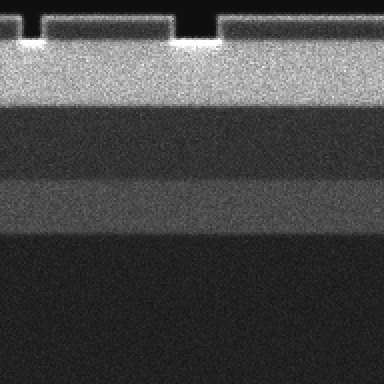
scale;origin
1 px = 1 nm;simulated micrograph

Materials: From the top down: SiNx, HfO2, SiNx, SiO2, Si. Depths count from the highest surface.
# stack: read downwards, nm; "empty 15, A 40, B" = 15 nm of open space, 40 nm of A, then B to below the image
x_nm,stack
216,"empty 24, HfO2 66, SiNx 74, SiO2 54, Si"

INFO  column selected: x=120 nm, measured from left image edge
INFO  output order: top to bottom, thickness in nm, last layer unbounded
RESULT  SiNx 24, HfO2 66, SiNx 74, SiO2 54, Si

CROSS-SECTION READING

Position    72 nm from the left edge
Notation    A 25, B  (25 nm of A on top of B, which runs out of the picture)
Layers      SiNx 24, HfO2 66, SiNx 74, SiO2 54, Si